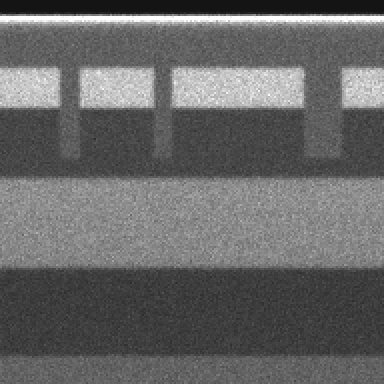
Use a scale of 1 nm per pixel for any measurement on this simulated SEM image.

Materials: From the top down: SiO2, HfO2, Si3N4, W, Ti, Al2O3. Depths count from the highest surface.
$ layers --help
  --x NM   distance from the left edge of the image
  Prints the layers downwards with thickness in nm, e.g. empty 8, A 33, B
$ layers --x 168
SiO2 142, Si3N4 20, W 90, Ti 88, Al2O3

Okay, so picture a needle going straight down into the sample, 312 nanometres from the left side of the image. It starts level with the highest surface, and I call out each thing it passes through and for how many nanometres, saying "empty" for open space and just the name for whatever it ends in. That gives SiO2 142, Si3N4 20, W 90, Ti 88, Al2O3